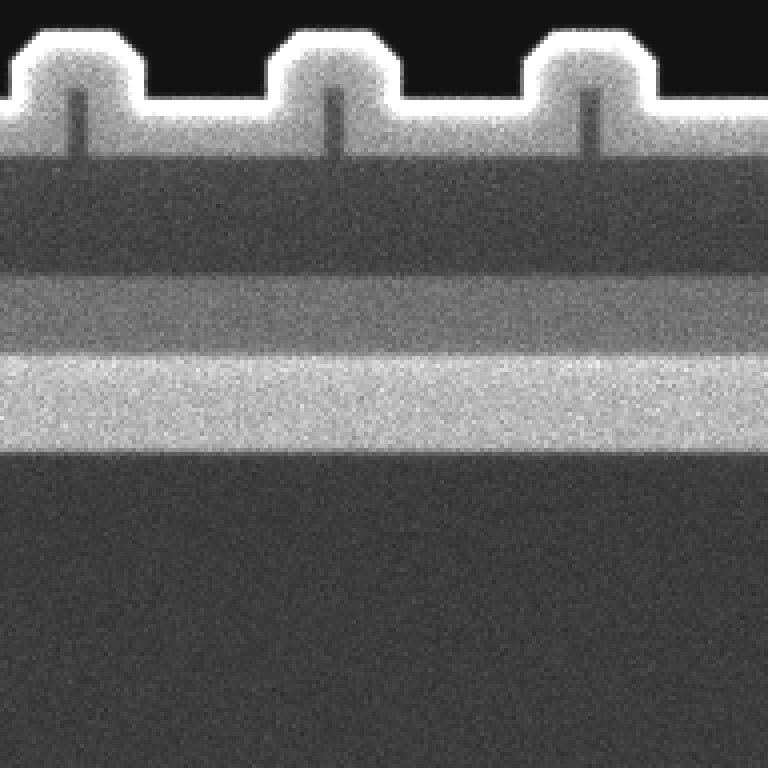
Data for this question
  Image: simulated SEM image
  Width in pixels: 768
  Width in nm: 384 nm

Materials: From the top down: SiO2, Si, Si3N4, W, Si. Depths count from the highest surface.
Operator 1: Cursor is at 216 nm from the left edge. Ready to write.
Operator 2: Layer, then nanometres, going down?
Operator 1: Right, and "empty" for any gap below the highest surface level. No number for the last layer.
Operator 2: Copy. empty 34, SiO2 28, Si 60, Si3N4 40, W 48, Si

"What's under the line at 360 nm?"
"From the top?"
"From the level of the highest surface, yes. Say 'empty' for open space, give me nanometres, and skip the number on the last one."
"empty 34, SiO2 28, Si 60, Si3N4 40, W 48, Si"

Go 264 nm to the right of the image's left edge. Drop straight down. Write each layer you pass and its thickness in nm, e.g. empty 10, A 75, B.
empty 12, SiO2 50, Si 60, Si3N4 40, W 48, Si